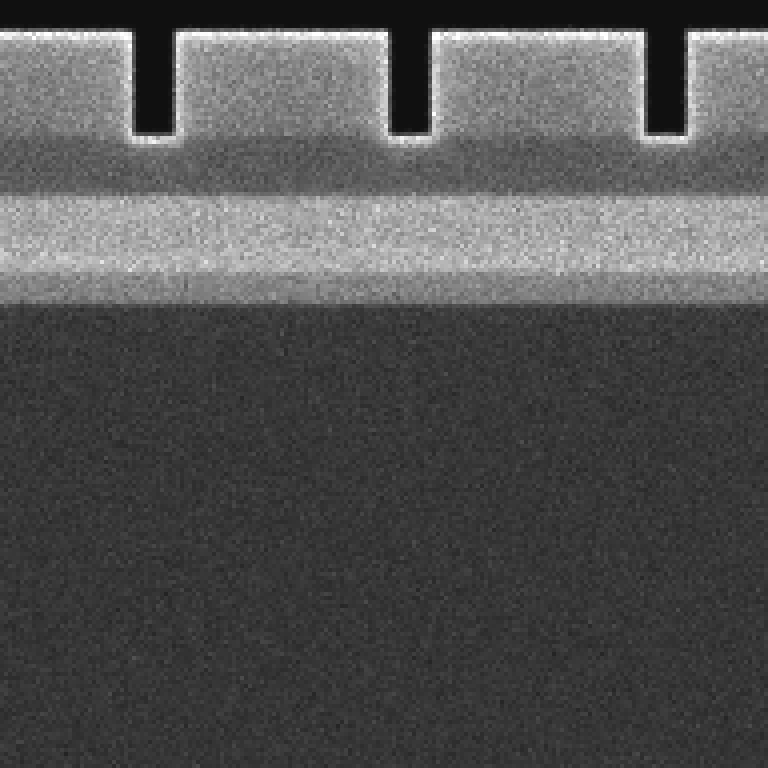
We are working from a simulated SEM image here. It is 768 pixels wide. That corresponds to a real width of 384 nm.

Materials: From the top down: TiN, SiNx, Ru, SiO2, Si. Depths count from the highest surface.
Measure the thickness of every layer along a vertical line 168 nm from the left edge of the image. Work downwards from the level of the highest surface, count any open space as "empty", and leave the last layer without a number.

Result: TiN 52, SiNx 30, Ru 38, SiO2 16, Si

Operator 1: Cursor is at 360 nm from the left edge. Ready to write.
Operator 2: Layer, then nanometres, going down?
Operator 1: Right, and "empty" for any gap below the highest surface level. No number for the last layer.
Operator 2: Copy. TiN 52, SiNx 30, Ru 38, SiO2 16, Si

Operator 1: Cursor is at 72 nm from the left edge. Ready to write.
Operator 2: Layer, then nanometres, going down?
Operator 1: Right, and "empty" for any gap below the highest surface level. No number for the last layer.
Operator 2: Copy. empty 52, SiNx 30, Ru 38, SiO2 16, Si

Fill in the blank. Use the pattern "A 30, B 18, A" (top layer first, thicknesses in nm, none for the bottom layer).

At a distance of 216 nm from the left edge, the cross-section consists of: TiN 52, SiNx 30, Ru 38, SiO2 16, Si